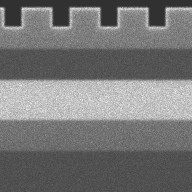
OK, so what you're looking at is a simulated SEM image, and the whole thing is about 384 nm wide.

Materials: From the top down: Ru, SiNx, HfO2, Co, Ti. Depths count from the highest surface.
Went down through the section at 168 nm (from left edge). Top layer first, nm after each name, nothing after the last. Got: Ru 82, SiNx 62, HfO2 80, Co 62, Ti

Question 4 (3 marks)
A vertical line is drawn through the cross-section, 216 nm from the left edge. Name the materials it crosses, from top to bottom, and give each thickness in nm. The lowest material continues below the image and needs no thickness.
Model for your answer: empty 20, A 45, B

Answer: empty 38, Ru 44, SiNx 62, HfO2 80, Co 62, Ti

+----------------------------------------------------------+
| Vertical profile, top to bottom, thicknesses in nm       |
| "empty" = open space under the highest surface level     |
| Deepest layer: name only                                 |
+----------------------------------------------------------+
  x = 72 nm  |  Ru 82, SiNx 62, HfO2 80, Co 62, Ti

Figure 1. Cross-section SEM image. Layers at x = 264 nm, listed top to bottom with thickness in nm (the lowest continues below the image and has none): Ru 82, SiNx 62, HfO2 80, Co 62, Ti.